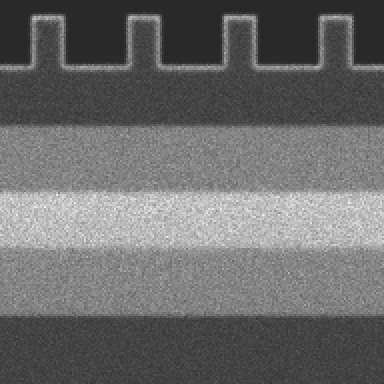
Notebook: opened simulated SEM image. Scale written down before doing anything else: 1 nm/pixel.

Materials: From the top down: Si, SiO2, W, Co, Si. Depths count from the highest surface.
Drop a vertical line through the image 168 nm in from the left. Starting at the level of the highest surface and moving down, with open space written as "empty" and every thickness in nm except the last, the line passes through empty 50, Si 60, SiO2 66, W 56, Co 68, Si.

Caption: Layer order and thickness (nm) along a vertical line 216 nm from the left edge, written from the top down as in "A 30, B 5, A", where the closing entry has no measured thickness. empty 50, Si 60, SiO2 66, W 56, Co 68, Si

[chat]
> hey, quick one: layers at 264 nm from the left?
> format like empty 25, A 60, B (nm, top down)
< empty 50, Si 60, SiO2 66, W 56, Co 68, Si